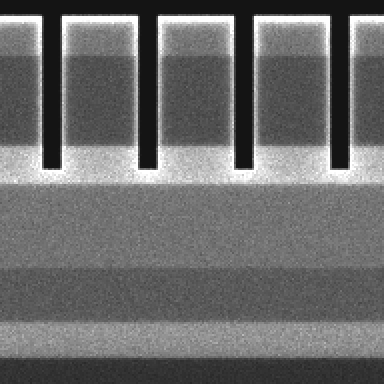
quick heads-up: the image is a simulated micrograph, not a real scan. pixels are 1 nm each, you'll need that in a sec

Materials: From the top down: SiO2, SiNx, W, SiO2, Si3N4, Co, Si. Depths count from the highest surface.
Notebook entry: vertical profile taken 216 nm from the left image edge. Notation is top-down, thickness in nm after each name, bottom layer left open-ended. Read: SiO2 40, SiNx 90, W 38, SiO2 84, Si3N4 54, Co 36, Si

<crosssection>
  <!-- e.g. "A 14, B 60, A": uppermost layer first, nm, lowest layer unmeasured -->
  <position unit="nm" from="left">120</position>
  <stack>SiO2 40, SiNx 90, W 38, SiO2 84, Si3N4 54, Co 36, Si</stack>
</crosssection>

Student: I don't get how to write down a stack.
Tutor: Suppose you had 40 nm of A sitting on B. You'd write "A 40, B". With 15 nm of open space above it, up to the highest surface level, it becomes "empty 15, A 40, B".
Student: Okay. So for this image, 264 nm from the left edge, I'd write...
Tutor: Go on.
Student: SiO2 40, SiNx 90, W 38, SiO2 84, Si3N4 54, Co 36, Si